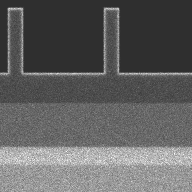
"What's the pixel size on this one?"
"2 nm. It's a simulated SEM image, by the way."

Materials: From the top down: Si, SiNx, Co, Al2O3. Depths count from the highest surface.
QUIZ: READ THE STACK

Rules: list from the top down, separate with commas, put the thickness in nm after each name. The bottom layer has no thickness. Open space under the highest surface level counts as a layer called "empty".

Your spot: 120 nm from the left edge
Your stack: empty 130, Si 60, SiNx 88, Co 36, Al2O3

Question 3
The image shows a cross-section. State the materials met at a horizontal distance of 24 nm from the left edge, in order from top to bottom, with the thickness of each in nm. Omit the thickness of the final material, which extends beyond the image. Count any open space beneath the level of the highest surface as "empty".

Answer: Si 190, SiNx 88, Co 36, Al2O3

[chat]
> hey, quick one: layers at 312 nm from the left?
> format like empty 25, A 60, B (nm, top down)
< empty 130, Si 60, SiNx 88, Co 36, Al2O3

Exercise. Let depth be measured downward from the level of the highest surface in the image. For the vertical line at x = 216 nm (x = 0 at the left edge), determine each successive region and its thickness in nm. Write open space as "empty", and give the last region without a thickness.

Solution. Si 190, SiNx 88, Co 36, Al2O3